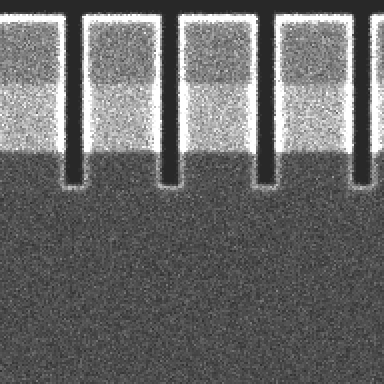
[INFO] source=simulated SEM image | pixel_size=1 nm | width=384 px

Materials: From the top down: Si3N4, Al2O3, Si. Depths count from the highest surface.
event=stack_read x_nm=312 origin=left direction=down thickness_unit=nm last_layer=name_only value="Si3N4 68, Al2O3 68, Si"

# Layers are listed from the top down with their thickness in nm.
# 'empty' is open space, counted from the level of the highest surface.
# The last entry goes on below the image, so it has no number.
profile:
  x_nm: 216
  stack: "Si3N4 68, Al2O3 68, Si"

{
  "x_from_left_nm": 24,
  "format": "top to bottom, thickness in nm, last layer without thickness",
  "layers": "Si3N4 68, Al2O3 68, Si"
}